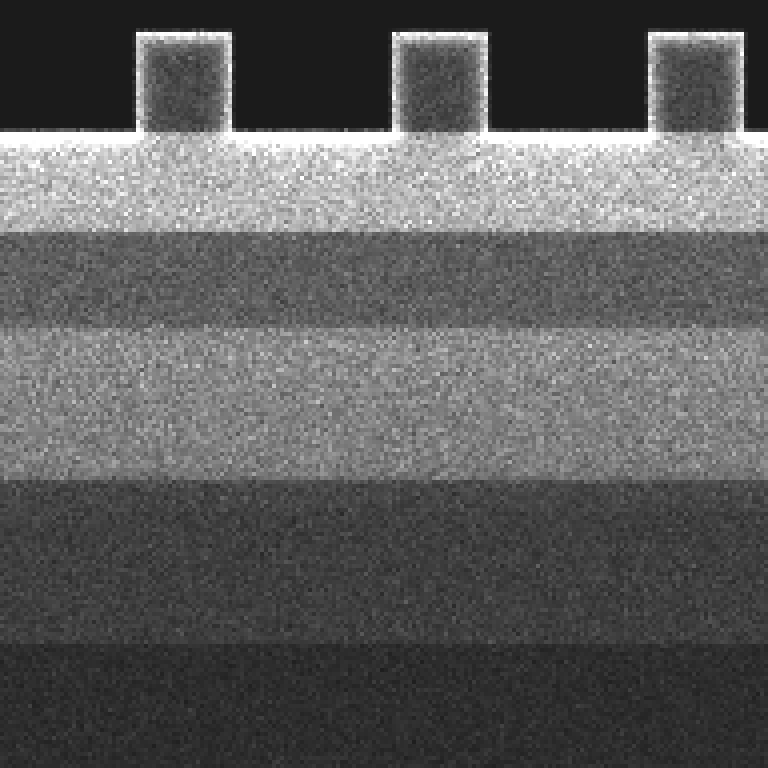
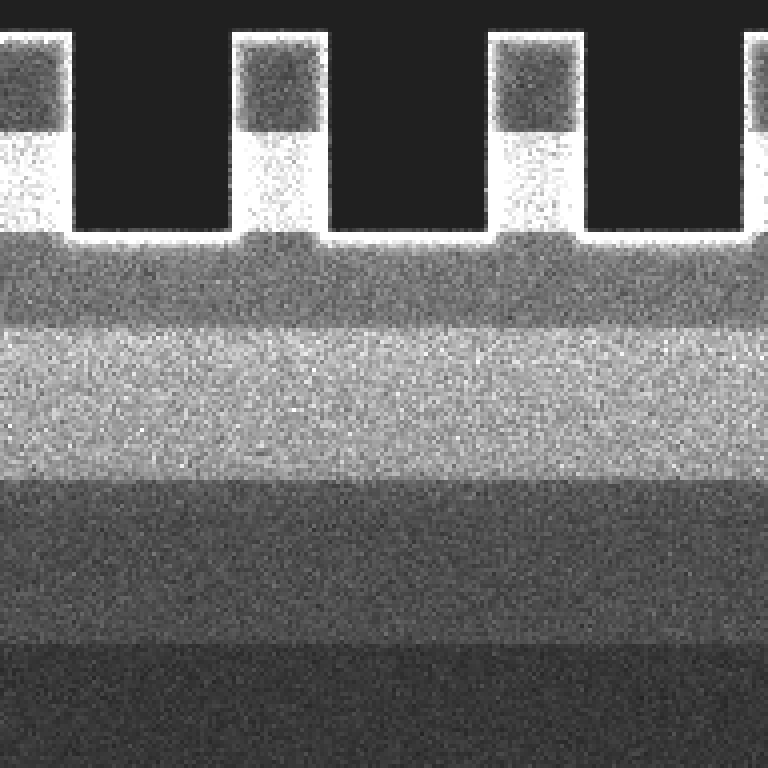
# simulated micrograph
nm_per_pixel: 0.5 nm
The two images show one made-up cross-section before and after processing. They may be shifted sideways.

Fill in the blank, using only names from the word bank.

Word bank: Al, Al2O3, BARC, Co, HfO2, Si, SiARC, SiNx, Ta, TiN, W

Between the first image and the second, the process removed HfO2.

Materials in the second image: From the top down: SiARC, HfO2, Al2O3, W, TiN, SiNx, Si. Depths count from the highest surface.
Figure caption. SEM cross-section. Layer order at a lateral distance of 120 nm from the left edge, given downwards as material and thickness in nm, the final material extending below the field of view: SiARC 50, HfO2 50, Al2O3 48, W 76, TiN 16, SiNx 66, Si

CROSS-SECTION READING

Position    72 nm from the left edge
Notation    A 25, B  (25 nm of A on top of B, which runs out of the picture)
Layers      empty 100, Al2O3 48, W 76, TiN 16, SiNx 66, Si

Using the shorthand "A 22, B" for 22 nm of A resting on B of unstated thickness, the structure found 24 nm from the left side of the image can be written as SiARC 50, HfO2 50, Al2O3 48, W 76, TiN 16, SiNx 66, Si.